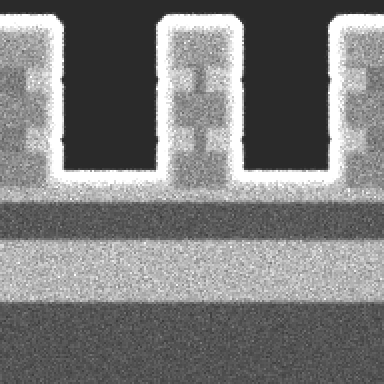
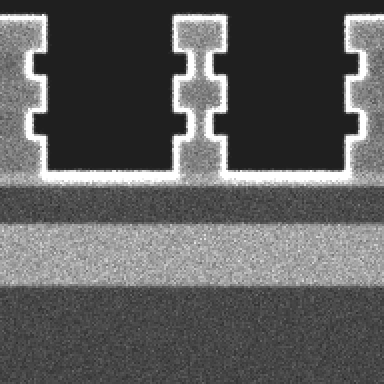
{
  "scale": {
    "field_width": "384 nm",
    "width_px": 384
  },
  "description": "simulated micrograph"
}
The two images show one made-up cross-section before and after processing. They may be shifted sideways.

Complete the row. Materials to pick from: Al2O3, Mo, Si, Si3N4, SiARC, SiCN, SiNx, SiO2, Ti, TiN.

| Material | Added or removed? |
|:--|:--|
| Al2O3 | removed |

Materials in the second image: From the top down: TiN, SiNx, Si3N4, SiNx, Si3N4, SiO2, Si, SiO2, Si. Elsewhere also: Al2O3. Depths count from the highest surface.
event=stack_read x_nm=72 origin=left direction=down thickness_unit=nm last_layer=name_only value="empty 156, SiO2 14, Si 38, SiO2 62, Si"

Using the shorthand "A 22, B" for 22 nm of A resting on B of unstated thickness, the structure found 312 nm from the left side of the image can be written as empty 156, SiO2 14, Si 38, SiO2 62, Si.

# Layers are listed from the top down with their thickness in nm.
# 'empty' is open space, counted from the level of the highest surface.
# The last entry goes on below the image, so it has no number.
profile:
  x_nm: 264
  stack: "empty 156, SiO2 14, Si 38, SiO2 62, Si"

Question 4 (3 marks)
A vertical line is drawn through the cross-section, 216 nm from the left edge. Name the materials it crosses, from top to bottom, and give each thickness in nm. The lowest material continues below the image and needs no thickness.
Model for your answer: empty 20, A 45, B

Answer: TiN 36, empty 24, Si3N4 36, empty 24, Si3N4 36, SiO2 14, Si 38, SiO2 62, Si